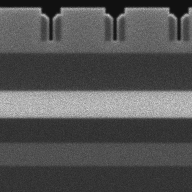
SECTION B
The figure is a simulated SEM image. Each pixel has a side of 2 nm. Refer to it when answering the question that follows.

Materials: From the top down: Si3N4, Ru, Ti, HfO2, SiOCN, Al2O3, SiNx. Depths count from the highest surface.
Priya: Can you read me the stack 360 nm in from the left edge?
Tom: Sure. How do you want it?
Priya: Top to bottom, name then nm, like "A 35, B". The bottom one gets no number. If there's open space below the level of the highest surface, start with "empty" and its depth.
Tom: empty 66, Ru 24, Ti 76, HfO2 54, SiOCN 50, Al2O3 46, SiNx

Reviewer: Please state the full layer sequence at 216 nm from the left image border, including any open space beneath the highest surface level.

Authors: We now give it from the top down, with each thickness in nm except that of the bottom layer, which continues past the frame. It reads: empty 12, Si3N4 54, Ru 24, Ti 76, HfO2 54, SiOCN 50, Al2O3 46, SiNx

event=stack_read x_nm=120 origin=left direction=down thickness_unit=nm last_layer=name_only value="empty 12, Si3N4 54, Ru 24, Ti 76, HfO2 54, SiOCN 50, Al2O3 46, SiNx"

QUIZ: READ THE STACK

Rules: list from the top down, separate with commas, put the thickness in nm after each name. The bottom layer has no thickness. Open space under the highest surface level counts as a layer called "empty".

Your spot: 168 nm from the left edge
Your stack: Ru 90, Ti 76, HfO2 54, SiOCN 50, Al2O3 46, SiNx